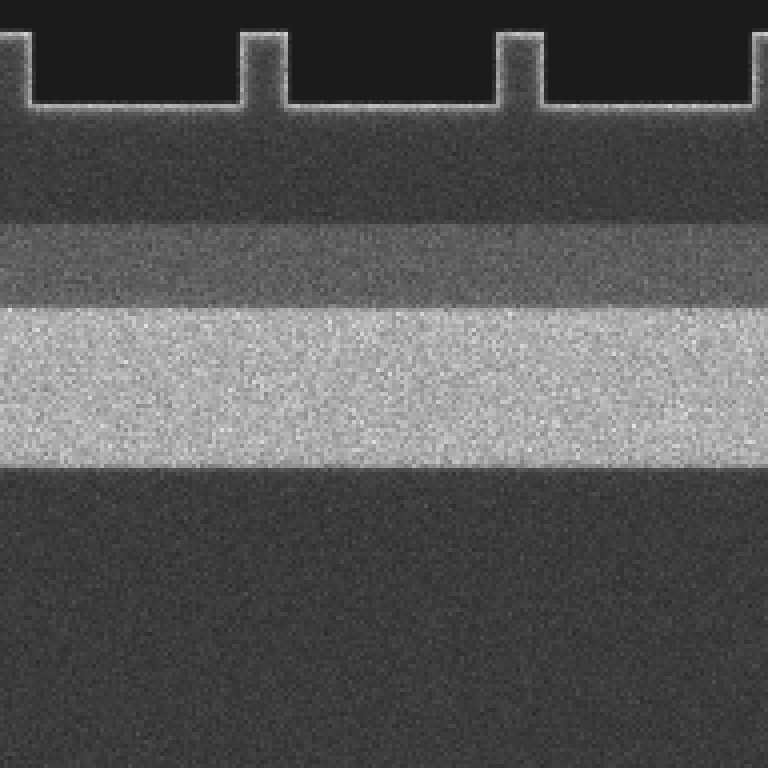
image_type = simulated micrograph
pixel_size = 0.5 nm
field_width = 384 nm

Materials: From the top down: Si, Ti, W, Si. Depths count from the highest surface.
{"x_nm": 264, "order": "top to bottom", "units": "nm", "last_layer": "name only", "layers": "Si 96, Ti 42, W 80, Si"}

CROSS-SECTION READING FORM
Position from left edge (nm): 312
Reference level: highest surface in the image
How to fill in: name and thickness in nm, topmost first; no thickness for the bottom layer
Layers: empty 36, Si 60, Ti 42, W 80, Si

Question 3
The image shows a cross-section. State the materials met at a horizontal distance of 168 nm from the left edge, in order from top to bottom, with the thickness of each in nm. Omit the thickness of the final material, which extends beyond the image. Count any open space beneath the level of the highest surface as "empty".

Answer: empty 36, Si 60, Ti 42, W 80, Si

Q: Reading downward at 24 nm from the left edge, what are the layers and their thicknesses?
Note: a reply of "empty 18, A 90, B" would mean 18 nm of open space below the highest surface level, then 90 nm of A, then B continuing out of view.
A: empty 36, Si 60, Ti 42, W 80, Si